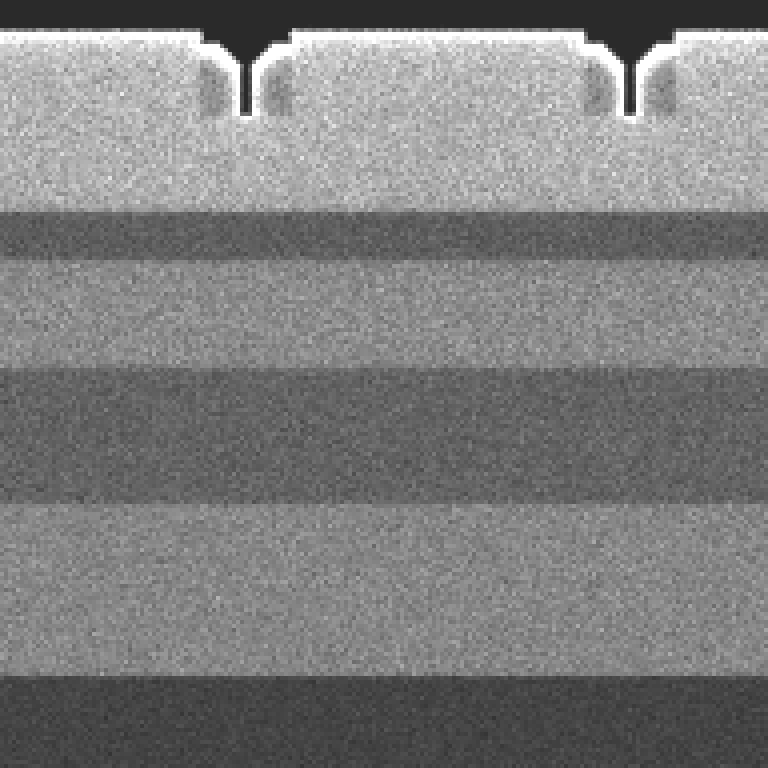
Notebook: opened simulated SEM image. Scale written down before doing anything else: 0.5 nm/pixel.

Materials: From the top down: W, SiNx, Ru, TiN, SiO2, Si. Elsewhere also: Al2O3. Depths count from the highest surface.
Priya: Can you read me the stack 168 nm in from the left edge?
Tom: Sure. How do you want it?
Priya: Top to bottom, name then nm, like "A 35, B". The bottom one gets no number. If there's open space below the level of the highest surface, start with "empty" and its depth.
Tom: W 90, SiNx 24, Ru 54, TiN 68, SiO2 86, Si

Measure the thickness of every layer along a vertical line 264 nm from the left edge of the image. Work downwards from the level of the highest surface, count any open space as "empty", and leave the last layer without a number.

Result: W 90, SiNx 24, Ru 54, TiN 68, SiO2 86, Si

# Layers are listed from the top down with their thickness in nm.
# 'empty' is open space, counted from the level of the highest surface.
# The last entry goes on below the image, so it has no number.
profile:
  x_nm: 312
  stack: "empty 42, W 48, SiNx 24, Ru 54, TiN 68, SiO2 86, Si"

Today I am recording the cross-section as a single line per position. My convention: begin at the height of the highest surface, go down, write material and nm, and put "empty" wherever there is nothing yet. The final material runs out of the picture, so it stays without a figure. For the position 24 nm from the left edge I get W 90, SiNx 24, Ru 54, TiN 68, SiO2 86, Si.